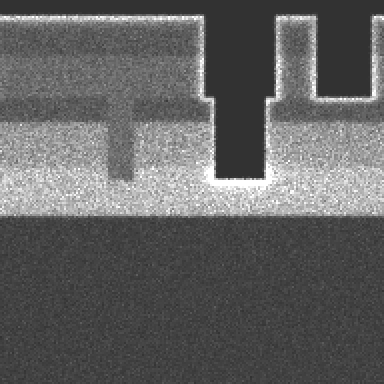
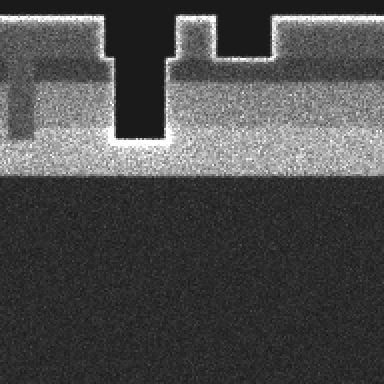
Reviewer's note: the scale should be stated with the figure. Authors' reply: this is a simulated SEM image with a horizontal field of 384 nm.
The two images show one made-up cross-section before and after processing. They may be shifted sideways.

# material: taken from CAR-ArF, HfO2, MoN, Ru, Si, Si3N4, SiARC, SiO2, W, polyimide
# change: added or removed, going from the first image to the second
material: SiARC
change: removed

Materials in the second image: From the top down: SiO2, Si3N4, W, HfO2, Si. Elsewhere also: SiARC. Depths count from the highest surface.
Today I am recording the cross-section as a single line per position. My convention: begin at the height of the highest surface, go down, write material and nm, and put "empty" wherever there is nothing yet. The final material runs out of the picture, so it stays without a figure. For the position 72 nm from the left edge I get SiO2 42, Si3N4 24, W 46, HfO2 48, Si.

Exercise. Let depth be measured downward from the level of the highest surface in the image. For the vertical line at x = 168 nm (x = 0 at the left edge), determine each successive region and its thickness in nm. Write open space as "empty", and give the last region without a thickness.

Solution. empty 42, Si3N4 24, W 46, HfO2 48, Si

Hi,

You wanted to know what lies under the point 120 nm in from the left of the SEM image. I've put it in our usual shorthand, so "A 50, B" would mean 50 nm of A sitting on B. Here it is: empty 124, HfO2 36, Si